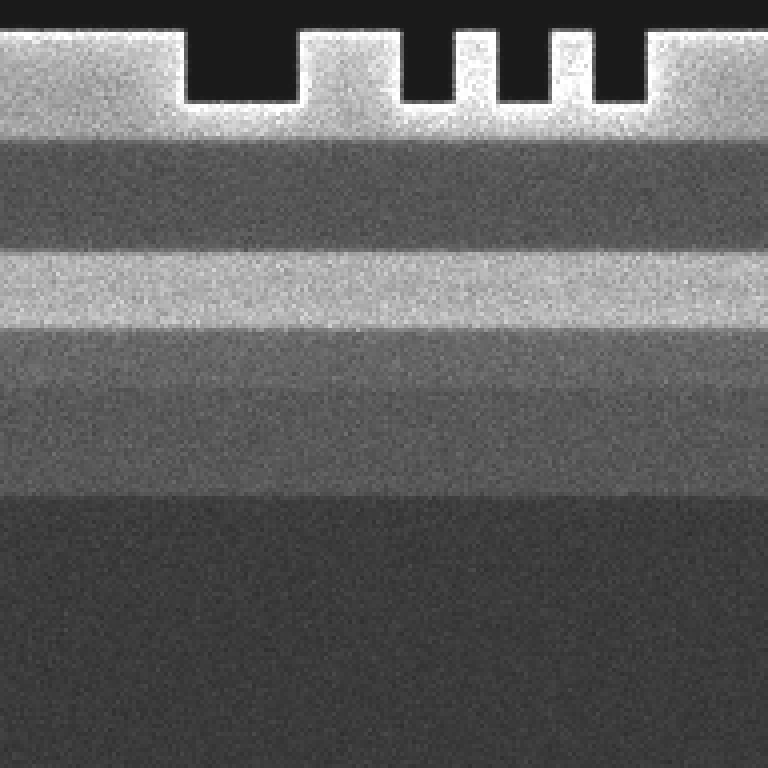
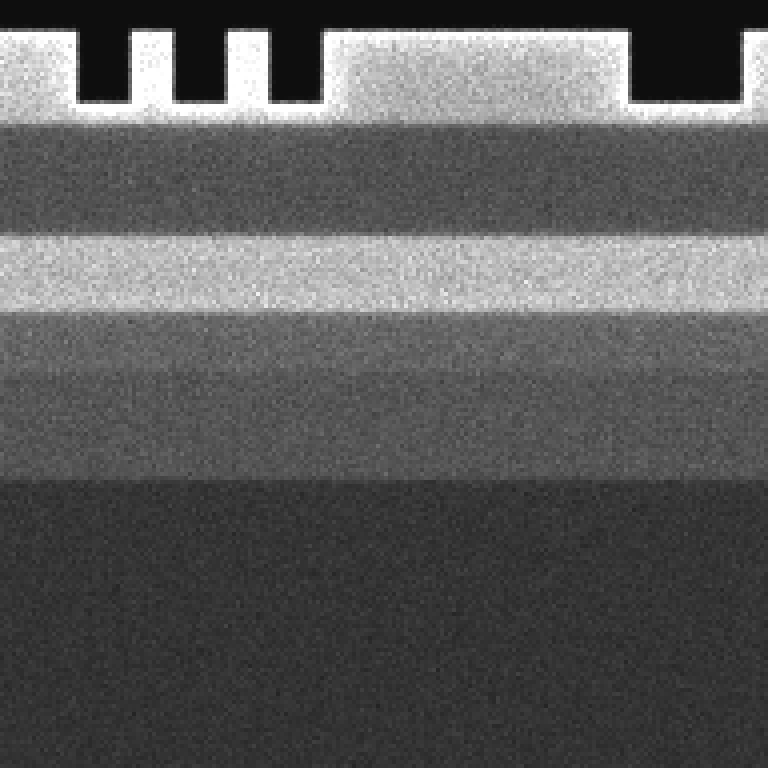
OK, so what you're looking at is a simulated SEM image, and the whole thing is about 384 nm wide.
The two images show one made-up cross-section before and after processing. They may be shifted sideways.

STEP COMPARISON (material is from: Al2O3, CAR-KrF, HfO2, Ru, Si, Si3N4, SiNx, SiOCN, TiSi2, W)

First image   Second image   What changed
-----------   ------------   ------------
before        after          Ru, removed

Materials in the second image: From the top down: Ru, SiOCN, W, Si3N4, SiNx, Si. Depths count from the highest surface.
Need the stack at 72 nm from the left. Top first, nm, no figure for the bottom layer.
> Ru 46, SiOCN 56, W 38, Si3N4 30, SiNx 54, Si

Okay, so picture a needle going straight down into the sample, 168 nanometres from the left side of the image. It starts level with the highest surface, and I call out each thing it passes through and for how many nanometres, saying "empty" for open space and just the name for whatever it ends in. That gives Ru 46, SiOCN 56, W 38, Si3N4 30, SiNx 54, Si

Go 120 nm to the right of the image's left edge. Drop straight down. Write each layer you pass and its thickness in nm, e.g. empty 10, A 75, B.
Ru 46, SiOCN 56, W 38, Si3N4 30, SiNx 54, Si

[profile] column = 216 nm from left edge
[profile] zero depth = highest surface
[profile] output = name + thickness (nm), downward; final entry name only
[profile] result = Ru 46, SiOCN 56, W 38, Si3N4 30, SiNx 54, Si